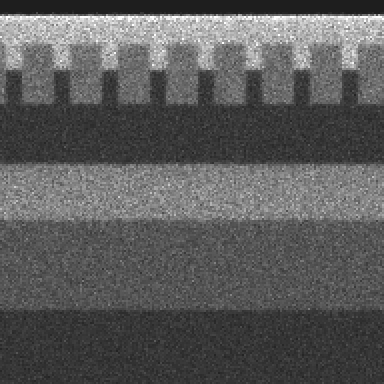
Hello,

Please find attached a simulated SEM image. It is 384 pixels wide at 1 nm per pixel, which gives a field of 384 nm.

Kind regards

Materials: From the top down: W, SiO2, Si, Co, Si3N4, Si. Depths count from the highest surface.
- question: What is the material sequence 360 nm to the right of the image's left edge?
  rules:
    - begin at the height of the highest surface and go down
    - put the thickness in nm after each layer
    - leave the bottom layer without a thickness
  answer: W 28, SiO2 60, Si 60, Co 56, Si3N4 90, Si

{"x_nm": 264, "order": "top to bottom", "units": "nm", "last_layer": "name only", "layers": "W 28, SiO2 60, Si 60, Co 56, Si3N4 90, Si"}